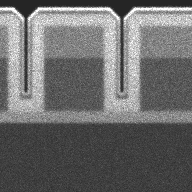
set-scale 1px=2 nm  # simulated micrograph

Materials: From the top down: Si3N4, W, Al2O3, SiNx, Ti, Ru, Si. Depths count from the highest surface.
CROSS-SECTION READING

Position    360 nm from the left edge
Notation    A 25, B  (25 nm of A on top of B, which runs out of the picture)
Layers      Si3N4 12, W 24, Al2O3 64, SiNx 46, Ti 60, Ru 24, Si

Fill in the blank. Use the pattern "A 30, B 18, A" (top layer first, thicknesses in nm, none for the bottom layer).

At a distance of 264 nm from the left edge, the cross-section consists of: empty 4, Si3N4 12, W 190, Ru 24, Si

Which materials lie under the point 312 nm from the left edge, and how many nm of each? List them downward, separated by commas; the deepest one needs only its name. Si3N4 12, W 24, Al2O3 64, SiNx 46, Ti 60, Ru 24, Si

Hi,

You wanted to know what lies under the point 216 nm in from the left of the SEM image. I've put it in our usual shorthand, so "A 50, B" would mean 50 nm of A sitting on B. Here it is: Si3N4 12, W 194, Ru 24, Si